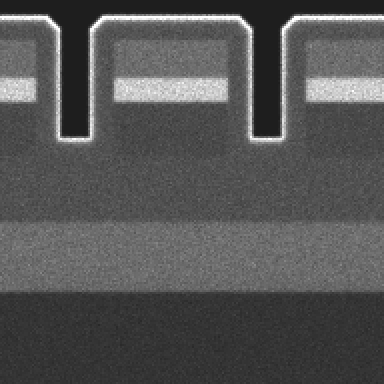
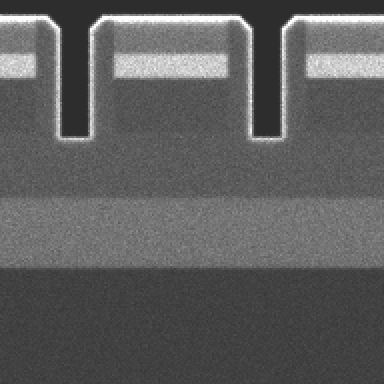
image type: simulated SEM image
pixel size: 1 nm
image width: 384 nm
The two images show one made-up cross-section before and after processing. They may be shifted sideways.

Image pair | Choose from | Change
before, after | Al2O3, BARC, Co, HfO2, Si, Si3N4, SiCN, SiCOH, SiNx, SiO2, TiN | Si3N4 (removed)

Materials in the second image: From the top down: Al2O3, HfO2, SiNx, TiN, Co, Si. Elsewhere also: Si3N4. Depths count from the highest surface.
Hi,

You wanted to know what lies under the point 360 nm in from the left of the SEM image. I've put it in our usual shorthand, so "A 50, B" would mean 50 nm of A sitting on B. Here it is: Al2O3 38, HfO2 24, SiNx 54, TiN 66, Co 70, Si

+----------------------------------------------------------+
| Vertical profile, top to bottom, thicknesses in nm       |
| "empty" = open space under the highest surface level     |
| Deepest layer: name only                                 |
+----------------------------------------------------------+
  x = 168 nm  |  Al2O3 38, HfO2 24, SiNx 54, TiN 66, Co 70, Si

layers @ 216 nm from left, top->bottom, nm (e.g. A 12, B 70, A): Al2O3 38, HfO2 24, SiNx 54, TiN 66, Co 70, Si